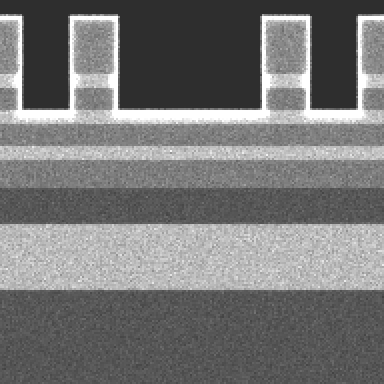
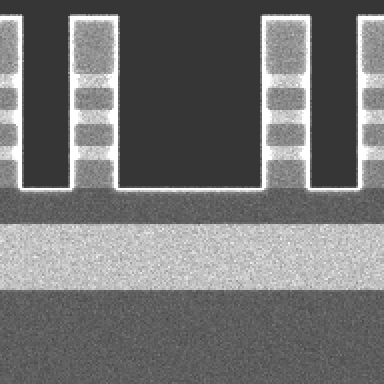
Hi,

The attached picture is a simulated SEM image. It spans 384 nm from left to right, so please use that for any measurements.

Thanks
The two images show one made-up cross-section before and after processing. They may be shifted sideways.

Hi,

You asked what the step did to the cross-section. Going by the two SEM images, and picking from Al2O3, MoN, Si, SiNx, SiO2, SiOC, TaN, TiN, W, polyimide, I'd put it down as Al2O3 and SiNx, removed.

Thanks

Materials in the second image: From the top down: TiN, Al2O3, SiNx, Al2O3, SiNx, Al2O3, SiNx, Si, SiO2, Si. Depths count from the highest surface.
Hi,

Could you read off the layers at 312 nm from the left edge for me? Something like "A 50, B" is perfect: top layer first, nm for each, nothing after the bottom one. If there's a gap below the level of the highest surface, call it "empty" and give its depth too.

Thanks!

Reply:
empty 172, Si 36, SiO2 66, Si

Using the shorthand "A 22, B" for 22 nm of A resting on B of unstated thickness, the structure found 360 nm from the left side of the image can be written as TiN 58, Al2O3 14, SiNx 22, Al2O3 14, SiNx 22, Al2O3 14, SiNx 28, Si 36, SiO2 66, Si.